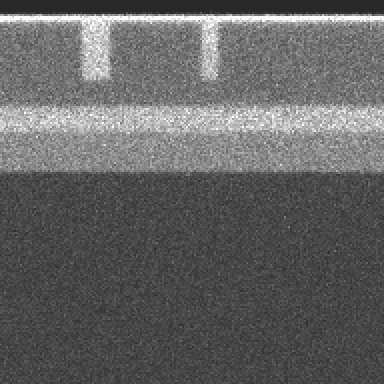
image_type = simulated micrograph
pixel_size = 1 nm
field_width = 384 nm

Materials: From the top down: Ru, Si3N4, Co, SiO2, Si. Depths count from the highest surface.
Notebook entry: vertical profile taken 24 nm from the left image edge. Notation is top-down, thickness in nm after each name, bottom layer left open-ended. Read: Si3N4 90, Co 26, SiO2 40, Si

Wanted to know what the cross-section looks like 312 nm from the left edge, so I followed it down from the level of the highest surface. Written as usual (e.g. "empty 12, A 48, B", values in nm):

Si3N4 90, Co 26, SiO2 40, Si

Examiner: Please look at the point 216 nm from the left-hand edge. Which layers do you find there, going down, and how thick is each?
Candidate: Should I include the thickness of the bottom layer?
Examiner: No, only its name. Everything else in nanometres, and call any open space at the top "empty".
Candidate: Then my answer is Ru 64, Si3N4 26, Co 26, SiO2 40, Si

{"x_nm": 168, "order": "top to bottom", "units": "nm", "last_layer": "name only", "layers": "Si3N4 90, Co 26, SiO2 40, Si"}